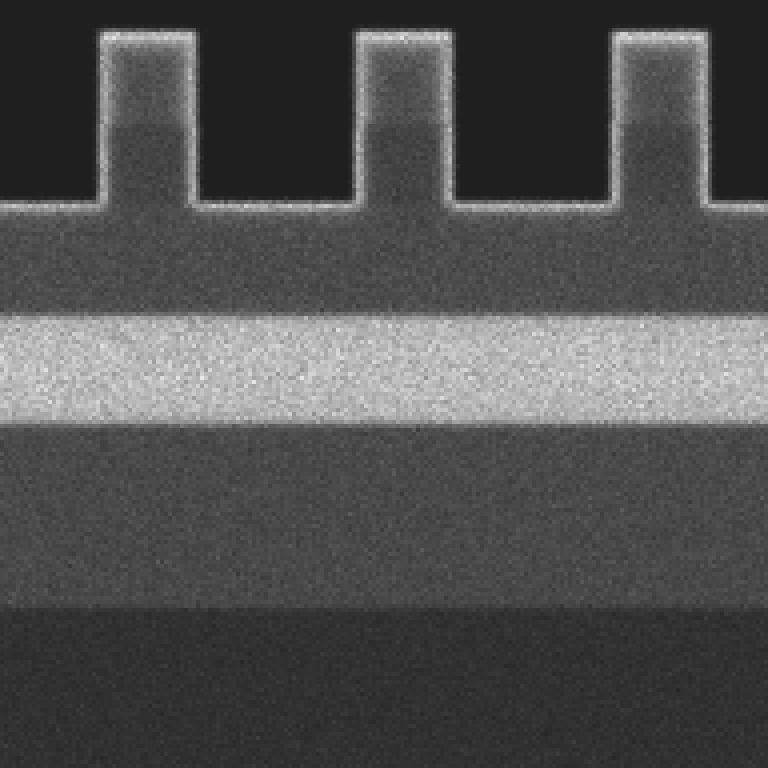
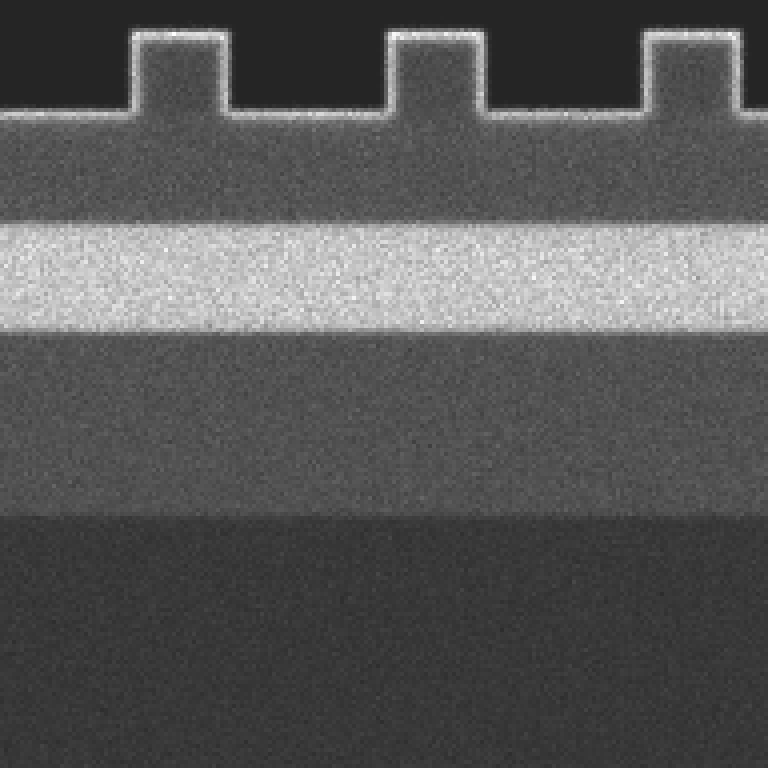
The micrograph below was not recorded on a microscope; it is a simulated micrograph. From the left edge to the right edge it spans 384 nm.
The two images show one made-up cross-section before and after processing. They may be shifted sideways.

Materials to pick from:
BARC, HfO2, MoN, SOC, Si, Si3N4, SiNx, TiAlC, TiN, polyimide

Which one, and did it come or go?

SOC - removed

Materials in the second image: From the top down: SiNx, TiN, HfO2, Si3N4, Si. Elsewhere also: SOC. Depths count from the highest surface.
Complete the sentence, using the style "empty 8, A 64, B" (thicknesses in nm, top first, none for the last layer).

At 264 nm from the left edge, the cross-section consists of empty 40, TiN 56, HfO2 54, Si3N4 92, Si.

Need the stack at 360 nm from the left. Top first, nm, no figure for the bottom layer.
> SiNx 40, TiN 56, HfO2 54, Si3N4 92, Si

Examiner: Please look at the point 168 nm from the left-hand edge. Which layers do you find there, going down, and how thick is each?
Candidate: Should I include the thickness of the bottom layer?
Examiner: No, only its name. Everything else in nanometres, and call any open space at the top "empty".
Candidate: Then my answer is empty 40, TiN 56, HfO2 54, Si3N4 92, Si